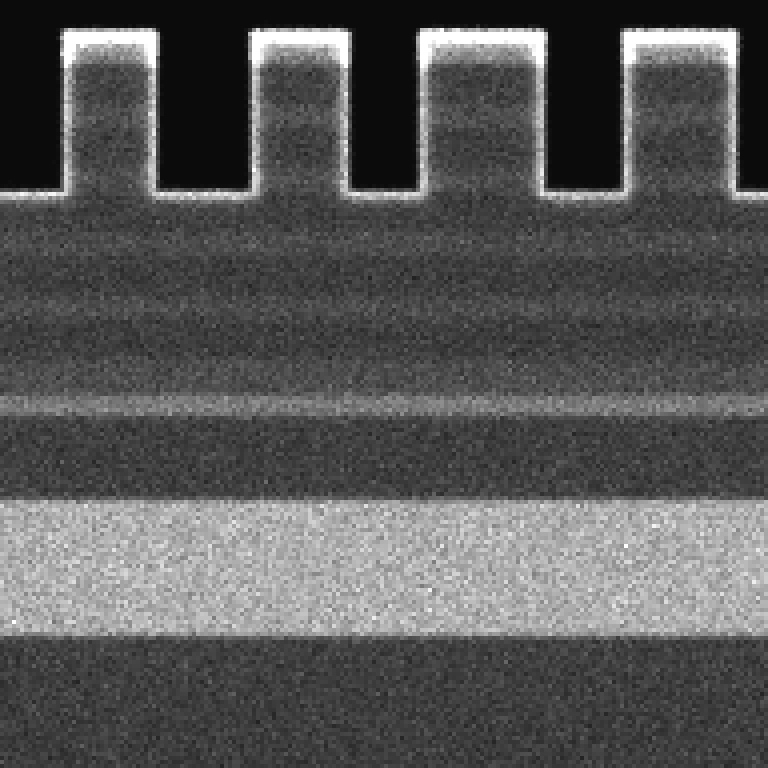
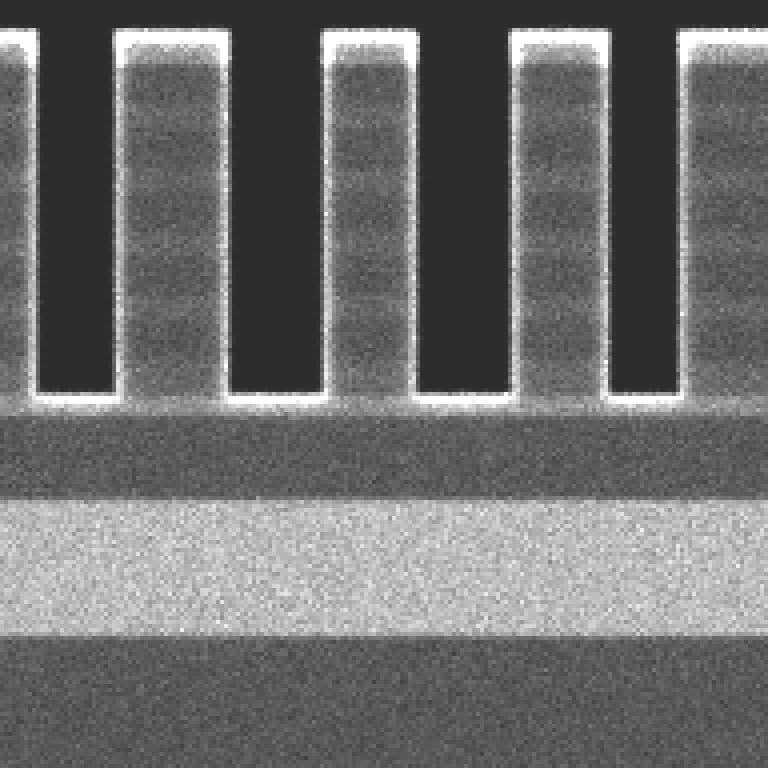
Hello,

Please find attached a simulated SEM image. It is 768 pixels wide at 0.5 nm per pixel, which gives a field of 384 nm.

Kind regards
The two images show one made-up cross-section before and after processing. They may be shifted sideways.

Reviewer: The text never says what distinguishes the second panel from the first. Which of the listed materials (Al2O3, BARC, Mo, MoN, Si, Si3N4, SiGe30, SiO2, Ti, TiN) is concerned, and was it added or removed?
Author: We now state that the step removed Si and SiGe30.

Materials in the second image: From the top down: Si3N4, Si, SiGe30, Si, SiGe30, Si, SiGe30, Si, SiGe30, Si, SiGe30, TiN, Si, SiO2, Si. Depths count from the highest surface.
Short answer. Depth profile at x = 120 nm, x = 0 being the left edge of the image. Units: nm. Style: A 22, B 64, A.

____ empty 182, TiN 10, Si 42, SiO2 68, Si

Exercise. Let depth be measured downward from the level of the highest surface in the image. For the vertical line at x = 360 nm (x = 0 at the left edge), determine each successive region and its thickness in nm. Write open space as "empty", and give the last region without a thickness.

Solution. Si3N4 16, Si 20, SiGe30 12, Si 20, SiGe30 12, Si 20, SiGe30 12, Si 20, SiGe30 12, Si 20, SiGe30 18, TiN 10, Si 42, SiO2 68, Si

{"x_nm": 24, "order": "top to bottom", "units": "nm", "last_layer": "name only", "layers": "empty 182, TiN 10, Si 42, SiO2 68, Si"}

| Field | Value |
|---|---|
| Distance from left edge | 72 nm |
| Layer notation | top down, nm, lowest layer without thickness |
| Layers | Si3N4 16, Si 20, SiGe30 12, Si 20, SiGe30 12, Si 20, SiGe30 12, Si 20, SiGe30 12, Si 20, SiGe30 18, TiN 10, Si 42, SiO2 68, Si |